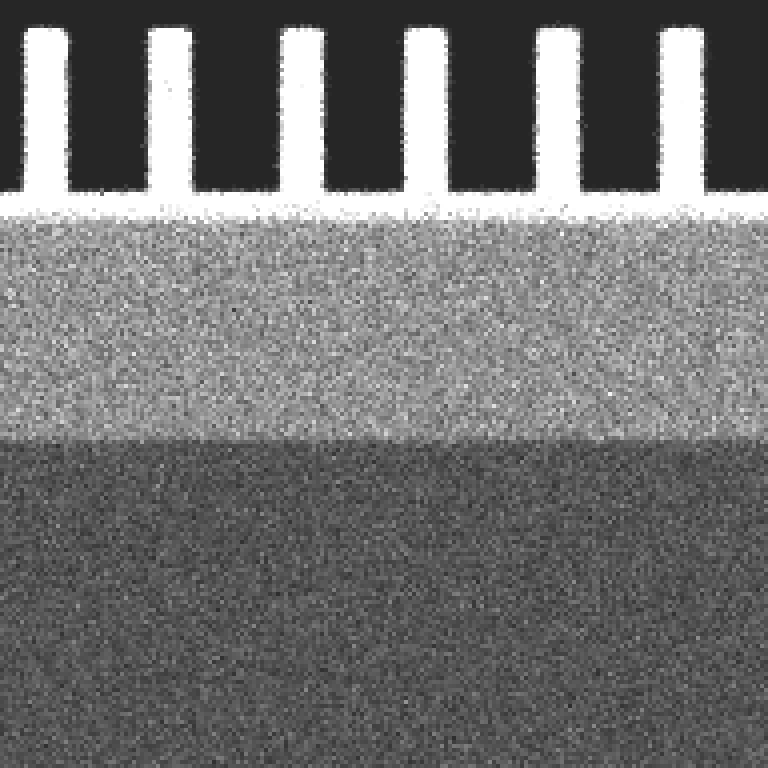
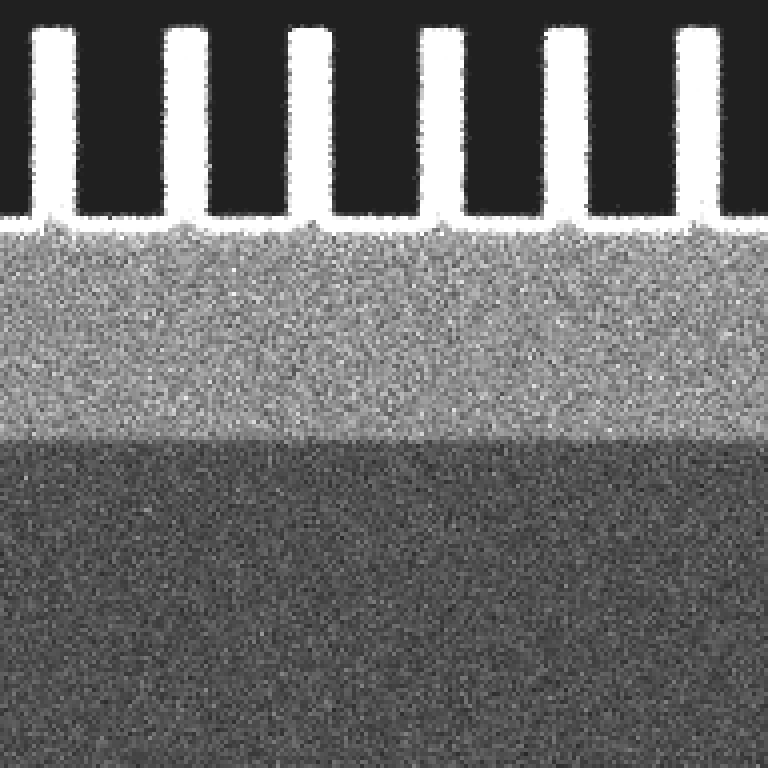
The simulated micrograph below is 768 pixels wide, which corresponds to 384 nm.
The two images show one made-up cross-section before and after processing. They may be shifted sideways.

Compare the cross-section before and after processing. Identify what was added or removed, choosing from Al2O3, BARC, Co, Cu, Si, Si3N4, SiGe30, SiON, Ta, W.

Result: Co removed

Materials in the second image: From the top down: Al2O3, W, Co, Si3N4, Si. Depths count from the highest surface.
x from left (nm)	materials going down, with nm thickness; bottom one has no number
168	empty 94, Si3N4 110, Si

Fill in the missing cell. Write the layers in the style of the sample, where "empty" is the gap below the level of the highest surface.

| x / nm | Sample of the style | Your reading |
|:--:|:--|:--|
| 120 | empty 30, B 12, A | empty 94, Si3N4 110, Si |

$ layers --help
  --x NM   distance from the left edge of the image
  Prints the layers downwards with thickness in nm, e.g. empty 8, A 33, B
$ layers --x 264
empty 94, Si3N4 110, Si